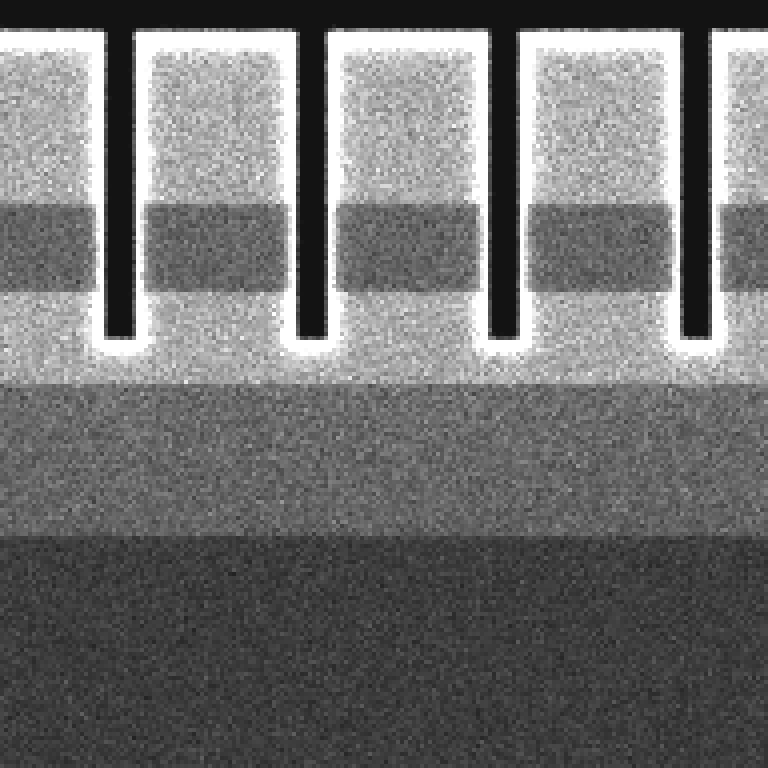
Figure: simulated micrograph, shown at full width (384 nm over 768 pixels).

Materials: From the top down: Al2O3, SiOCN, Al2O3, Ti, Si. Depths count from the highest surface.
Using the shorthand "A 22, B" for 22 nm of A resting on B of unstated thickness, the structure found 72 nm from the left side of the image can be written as Al2O3 86, SiOCN 44, Al2O3 46, Ti 76, Si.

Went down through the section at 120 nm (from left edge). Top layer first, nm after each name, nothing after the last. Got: Al2O3 86, SiOCN 44, Al2O3 46, Ti 76, Si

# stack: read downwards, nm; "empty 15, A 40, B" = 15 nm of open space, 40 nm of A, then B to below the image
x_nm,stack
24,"Al2O3 86, SiOCN 44, Al2O3 46, Ti 76, Si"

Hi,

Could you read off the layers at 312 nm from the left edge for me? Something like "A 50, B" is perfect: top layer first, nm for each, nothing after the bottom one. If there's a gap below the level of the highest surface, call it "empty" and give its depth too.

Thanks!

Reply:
Al2O3 86, SiOCN 44, Al2O3 46, Ti 76, Si